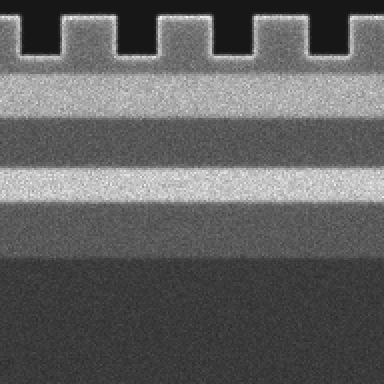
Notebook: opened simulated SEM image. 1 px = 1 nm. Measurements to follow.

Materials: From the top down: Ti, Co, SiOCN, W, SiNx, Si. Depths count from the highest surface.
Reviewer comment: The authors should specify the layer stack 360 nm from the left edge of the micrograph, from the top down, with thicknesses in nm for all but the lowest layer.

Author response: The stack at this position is Ti 58, Co 44, SiOCN 50, W 34, SiNx 56, Si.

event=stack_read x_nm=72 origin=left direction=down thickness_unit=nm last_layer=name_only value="Ti 58, Co 44, SiOCN 50, W 34, SiNx 56, Si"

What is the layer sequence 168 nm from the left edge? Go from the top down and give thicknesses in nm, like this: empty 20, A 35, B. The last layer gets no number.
Ti 58, Co 44, SiOCN 50, W 34, SiNx 56, Si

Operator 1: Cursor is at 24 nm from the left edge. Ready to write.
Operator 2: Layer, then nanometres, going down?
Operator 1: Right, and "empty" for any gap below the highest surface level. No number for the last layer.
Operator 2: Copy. empty 40, Ti 18, Co 44, SiOCN 50, W 34, SiNx 56, Si